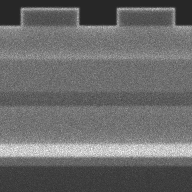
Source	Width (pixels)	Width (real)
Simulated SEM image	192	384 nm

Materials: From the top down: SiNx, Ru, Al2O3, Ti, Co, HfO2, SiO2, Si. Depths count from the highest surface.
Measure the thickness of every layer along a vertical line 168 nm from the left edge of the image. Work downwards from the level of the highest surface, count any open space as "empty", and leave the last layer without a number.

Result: empty 36, Ru 66, Al2O3 66, Ti 28, Co 76, HfO2 26, SiO2 18, Si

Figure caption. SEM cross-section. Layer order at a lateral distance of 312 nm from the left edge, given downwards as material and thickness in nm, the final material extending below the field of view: SiNx 36, Ru 66, Al2O3 66, Ti 28, Co 76, HfO2 26, SiO2 18, Si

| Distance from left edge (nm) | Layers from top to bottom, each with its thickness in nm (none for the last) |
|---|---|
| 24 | empty 36, Ru 66, Al2O3 66, Ti 28, Co 76, HfO2 26, SiO2 18, Si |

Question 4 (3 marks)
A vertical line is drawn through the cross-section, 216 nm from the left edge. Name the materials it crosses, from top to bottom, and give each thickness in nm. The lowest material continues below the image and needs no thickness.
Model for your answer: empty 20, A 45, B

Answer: empty 36, Ru 66, Al2O3 66, Ti 28, Co 76, HfO2 26, SiO2 18, Si